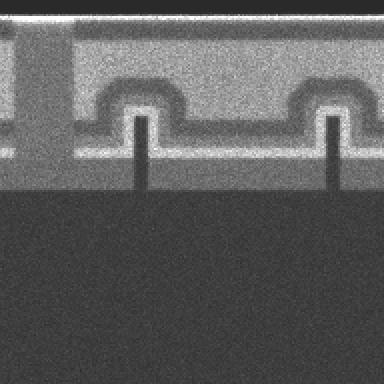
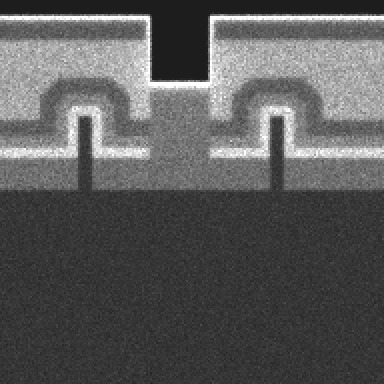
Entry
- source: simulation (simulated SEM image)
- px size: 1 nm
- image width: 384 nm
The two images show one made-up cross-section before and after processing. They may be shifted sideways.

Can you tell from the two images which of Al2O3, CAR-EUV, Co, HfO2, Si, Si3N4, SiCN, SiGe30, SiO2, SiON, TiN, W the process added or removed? Yes, it removed Al2O3.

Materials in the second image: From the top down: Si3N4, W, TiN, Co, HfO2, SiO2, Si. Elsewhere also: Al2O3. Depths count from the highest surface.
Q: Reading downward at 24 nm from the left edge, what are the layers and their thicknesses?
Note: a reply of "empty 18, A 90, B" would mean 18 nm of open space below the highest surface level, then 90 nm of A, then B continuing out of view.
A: Si3N4 24, W 80, TiN 16, Co 12, HfO2 10, SiO2 32, Si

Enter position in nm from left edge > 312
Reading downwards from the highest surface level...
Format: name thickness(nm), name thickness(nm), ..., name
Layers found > Si3N4 24, W 48, TiN 48, Co 12, HfO2 10, SiO2 32, Si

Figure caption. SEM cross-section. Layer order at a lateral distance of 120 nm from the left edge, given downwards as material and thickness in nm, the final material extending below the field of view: Si3N4 24, W 48, TiN 48, Co 12, HfO2 10, SiO2 32, Si